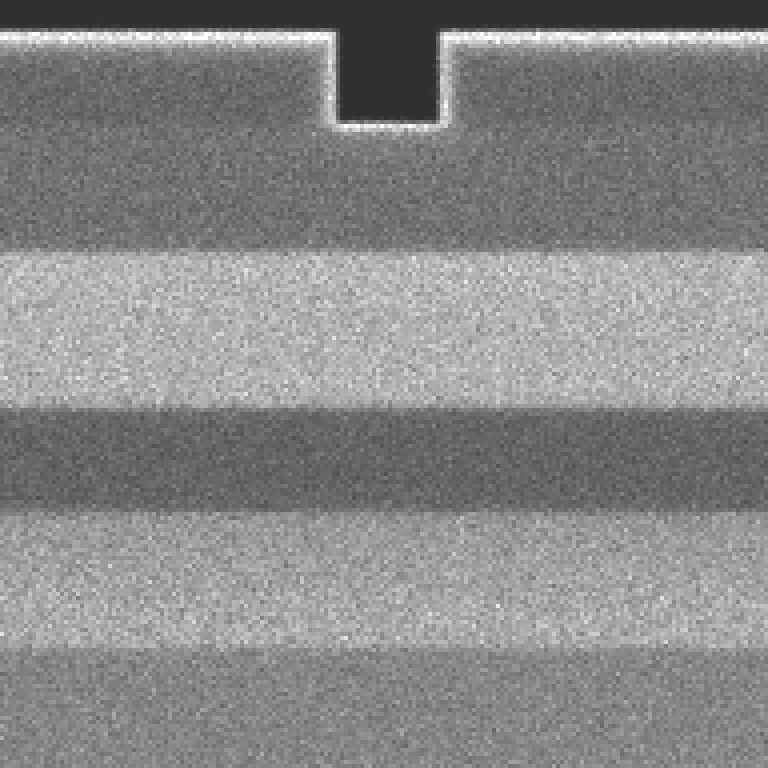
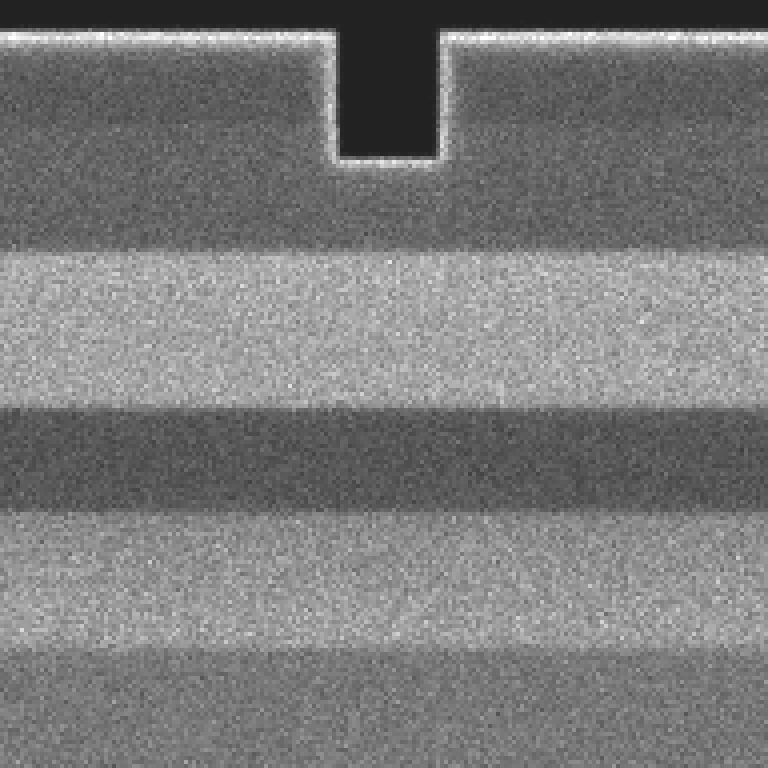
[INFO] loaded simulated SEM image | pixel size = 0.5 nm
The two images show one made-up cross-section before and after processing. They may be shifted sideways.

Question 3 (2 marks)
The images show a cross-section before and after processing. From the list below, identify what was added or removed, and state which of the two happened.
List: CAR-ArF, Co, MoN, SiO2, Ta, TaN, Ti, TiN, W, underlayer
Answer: TiN was removed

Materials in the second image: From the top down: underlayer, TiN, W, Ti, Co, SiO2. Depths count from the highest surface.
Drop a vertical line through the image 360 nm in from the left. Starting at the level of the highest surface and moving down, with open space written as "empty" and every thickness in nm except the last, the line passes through underlayer 46, TiN 64, W 78, Ti 52, Co 68, SiO2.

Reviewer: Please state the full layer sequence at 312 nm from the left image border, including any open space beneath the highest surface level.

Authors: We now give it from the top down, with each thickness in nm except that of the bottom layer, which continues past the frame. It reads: underlayer 46, TiN 64, W 78, Ti 52, Co 68, SiO2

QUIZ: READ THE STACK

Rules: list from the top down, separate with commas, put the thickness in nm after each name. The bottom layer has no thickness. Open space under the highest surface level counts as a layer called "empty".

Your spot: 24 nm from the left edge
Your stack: underlayer 46, TiN 64, W 78, Ti 52, Co 68, SiO2